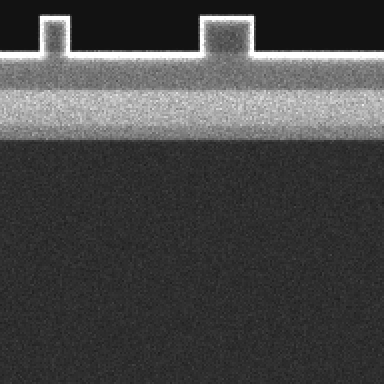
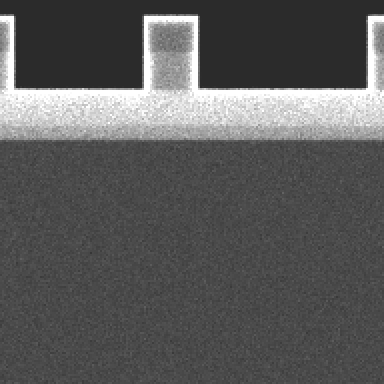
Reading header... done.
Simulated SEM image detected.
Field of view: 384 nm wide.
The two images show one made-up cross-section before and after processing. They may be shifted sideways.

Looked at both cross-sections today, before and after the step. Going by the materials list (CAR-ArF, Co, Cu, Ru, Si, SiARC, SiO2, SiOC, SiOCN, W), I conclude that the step removed SiO2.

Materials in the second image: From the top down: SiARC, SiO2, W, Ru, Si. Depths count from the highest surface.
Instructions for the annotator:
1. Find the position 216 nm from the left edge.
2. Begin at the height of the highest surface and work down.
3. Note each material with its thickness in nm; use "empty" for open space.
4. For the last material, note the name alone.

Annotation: empty 74, W 36, Ru 14, Si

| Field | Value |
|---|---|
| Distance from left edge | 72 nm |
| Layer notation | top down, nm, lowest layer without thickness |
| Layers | empty 74, W 36, Ru 14, Si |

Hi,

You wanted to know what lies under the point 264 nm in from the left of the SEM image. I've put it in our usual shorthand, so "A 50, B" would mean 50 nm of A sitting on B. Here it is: empty 74, W 36, Ru 14, Si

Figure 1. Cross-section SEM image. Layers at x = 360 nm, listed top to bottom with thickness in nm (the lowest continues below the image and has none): empty 74, W 36, Ru 14, Si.